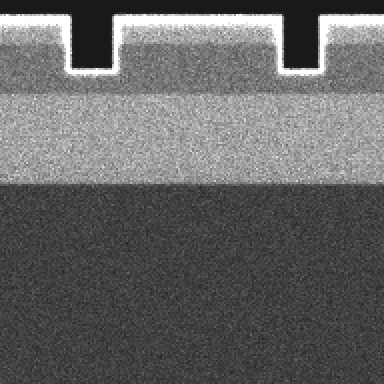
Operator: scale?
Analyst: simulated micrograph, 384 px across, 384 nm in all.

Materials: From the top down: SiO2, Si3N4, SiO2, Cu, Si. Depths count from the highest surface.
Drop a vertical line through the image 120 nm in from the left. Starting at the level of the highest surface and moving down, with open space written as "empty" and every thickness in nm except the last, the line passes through SiO2 28, Si3N4 50, SiO2 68, Cu 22, Si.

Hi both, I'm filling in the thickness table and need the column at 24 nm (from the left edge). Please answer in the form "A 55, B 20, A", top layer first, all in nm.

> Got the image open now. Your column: SiO2 28, Si3N4 50, SiO2 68, Cu 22, Si